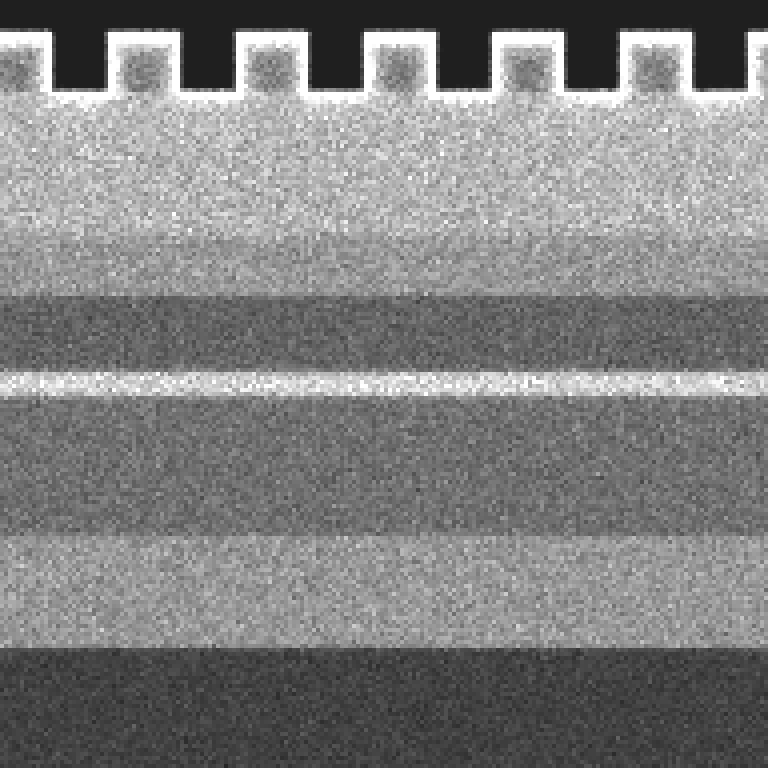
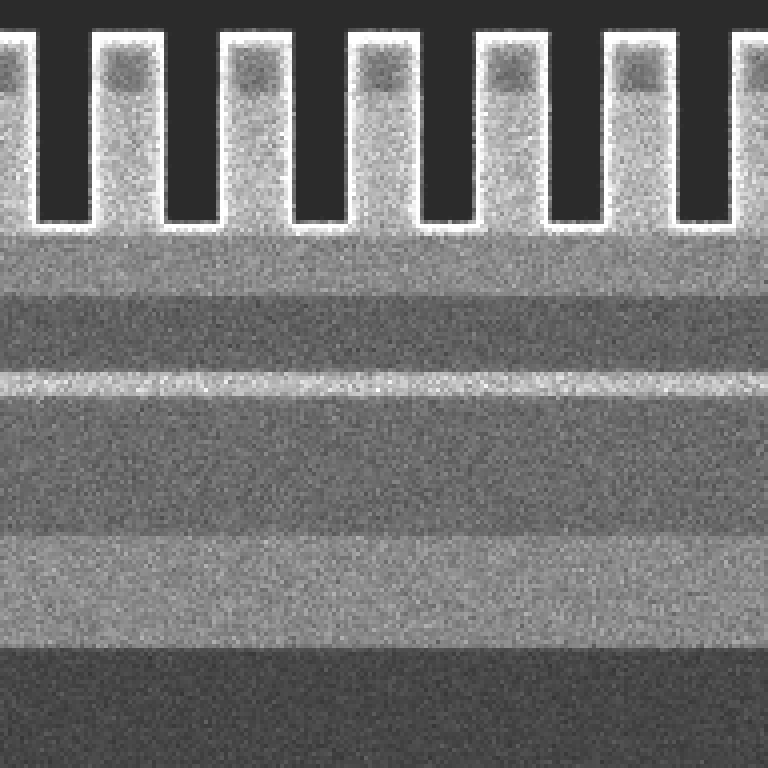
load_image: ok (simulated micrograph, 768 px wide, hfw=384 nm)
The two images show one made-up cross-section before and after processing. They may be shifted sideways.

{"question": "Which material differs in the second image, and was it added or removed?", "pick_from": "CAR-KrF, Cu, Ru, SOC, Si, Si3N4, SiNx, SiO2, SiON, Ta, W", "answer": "Ru, removed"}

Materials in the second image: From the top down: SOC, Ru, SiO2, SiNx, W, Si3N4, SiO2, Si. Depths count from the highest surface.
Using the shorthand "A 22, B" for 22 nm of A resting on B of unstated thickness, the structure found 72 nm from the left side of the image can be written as SOC 30, Ru 72, SiO2 30, SiNx 38, W 12, Si3N4 70, SiO2 56, Si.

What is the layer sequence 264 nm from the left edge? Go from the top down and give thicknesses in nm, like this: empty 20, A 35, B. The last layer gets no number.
SOC 30, Ru 72, SiO2 30, SiNx 38, W 12, Si3N4 70, SiO2 56, Si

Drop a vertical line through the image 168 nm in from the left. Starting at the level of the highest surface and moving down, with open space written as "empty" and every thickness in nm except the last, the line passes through empty 96, Ru 6, SiO2 30, SiNx 38, W 12, Si3N4 70, SiO2 56, Si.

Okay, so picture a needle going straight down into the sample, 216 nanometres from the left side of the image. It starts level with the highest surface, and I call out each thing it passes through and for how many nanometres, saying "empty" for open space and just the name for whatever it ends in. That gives empty 96, Ru 6, SiO2 30, SiNx 38, W 12, Si3N4 70, SiO2 56, Si